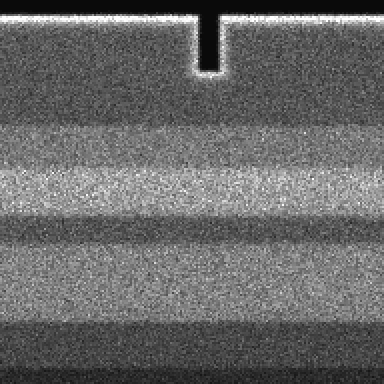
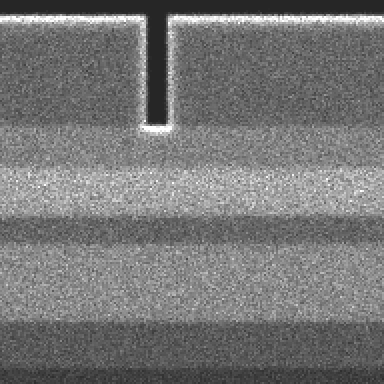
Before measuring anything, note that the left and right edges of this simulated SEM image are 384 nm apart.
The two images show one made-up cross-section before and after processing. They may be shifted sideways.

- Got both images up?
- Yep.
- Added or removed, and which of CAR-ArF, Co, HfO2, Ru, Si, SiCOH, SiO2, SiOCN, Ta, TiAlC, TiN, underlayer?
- removed, underlayer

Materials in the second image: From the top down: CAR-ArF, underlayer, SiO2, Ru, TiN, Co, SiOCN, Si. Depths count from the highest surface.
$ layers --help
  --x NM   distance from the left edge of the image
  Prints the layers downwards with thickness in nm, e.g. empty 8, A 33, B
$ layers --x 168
CAR-ArF 56, underlayer 54, SiO2 42, Ru 48, TiN 28, Co 78, SiOCN 46, Si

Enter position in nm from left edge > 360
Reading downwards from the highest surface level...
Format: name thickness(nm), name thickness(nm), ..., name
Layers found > CAR-ArF 56, underlayer 54, SiO2 42, Ru 48, TiN 28, Co 78, SiOCN 46, Si